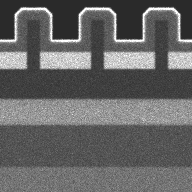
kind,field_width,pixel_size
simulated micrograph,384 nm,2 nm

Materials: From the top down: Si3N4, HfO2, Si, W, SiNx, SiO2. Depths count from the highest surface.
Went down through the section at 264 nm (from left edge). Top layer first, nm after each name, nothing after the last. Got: empty 64, Si3N4 24, HfO2 34, Si 60, W 52, SiNx 84, SiO2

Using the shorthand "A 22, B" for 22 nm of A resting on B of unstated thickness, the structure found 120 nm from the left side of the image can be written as empty 64, Si3N4 24, HfO2 34, Si 60, W 52, SiNx 84, SiO2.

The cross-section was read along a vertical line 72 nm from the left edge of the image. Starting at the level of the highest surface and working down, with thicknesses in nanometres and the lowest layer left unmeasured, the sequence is Si3N4 24, Si 158, W 52, SiNx 84, SiO2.